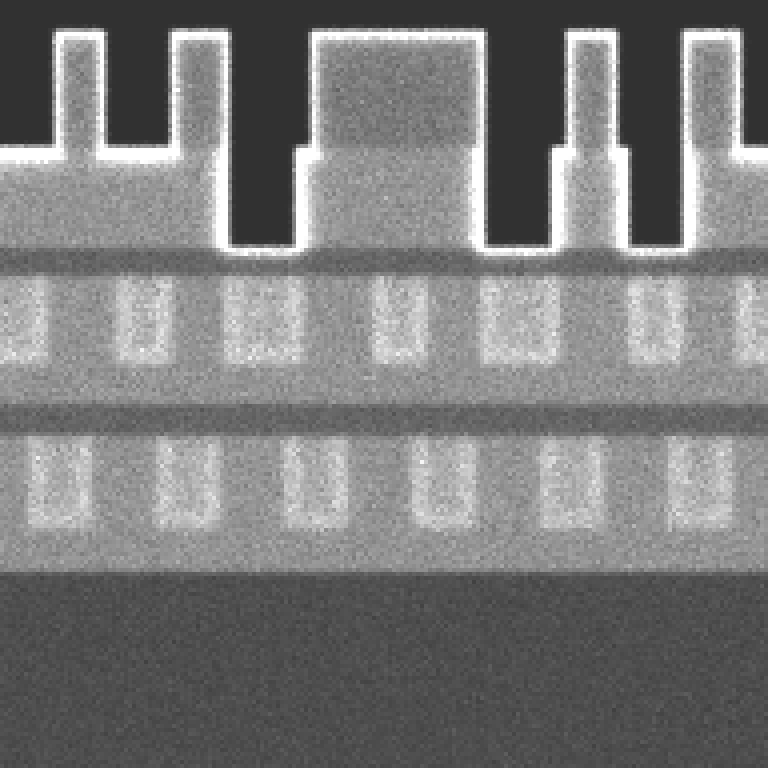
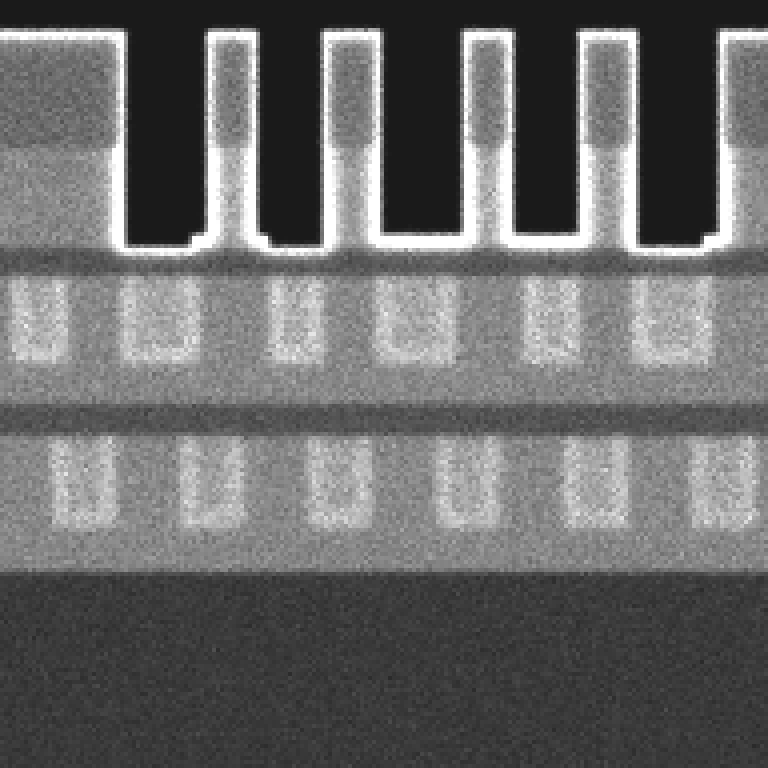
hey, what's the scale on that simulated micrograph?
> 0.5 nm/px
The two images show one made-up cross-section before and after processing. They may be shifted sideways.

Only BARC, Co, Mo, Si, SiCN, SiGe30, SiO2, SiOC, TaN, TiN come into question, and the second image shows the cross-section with SiO2 removed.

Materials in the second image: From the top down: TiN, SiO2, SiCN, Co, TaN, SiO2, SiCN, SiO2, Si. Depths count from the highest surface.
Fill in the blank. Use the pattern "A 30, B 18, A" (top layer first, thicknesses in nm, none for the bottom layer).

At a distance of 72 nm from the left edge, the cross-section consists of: empty 108, SiCN 14, Co 36, TaN 8, SiO2 20, SiCN 16, SiO2 68, Si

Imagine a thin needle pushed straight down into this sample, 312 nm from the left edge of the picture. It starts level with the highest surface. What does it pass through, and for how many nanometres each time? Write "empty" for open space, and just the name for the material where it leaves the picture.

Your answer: TiN 58, SiO2 50, SiCN 14, SiO2 64, SiCN 16, TaN 46, SiO2 22, Si